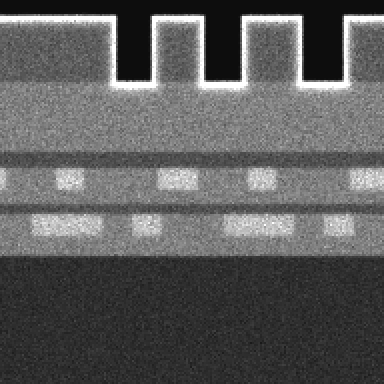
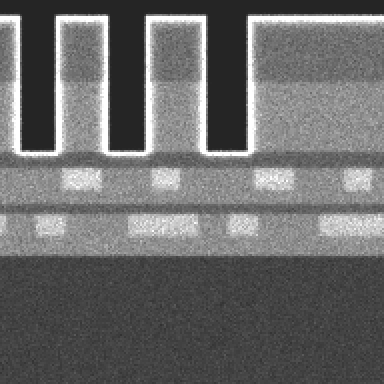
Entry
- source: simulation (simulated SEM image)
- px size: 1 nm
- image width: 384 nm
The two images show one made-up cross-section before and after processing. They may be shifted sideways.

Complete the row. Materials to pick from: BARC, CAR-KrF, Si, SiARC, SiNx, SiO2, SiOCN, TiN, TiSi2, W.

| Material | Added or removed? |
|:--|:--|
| SiO2 | removed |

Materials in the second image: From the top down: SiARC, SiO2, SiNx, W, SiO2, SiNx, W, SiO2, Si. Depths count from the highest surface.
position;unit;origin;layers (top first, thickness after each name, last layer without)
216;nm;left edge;empty 136, SiNx 16, SiO2 36, SiNx 10, SiO2 42, Si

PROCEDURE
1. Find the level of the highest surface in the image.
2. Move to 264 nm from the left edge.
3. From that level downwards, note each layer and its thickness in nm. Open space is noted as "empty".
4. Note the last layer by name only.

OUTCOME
SiARC 66, SiO2 70, SiNx 16, W 22, SiO2 14, SiNx 10, SiO2 42, Si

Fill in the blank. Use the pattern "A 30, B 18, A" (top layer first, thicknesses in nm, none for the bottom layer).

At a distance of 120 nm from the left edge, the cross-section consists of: empty 136, SiNx 16, SiO2 36, SiNx 10, SiO2 42, Si